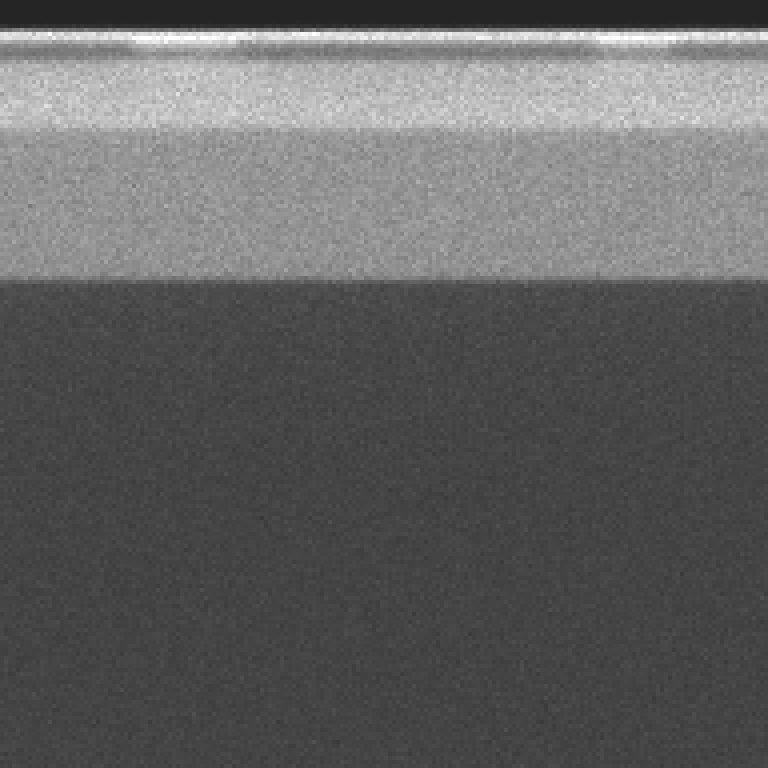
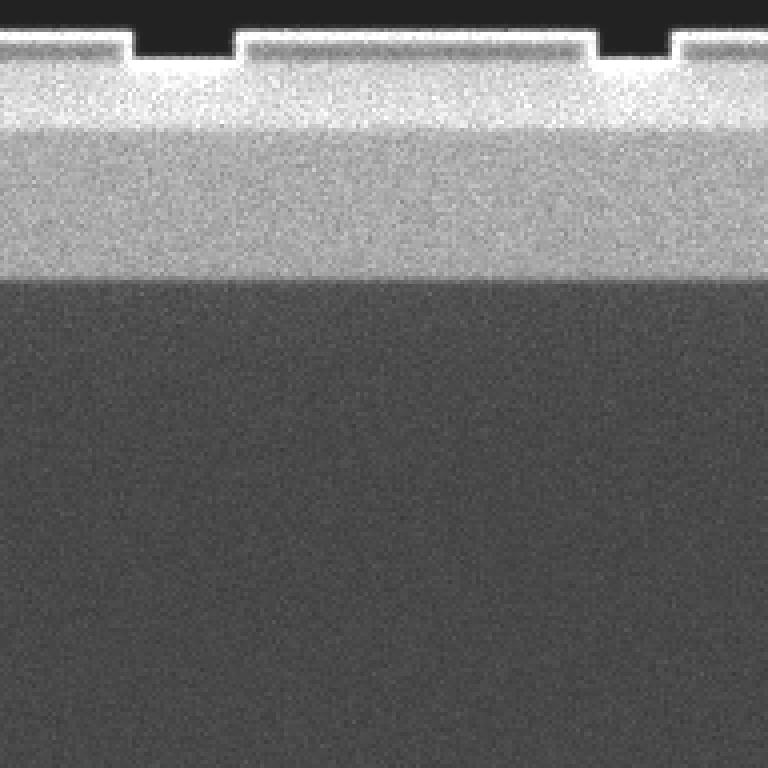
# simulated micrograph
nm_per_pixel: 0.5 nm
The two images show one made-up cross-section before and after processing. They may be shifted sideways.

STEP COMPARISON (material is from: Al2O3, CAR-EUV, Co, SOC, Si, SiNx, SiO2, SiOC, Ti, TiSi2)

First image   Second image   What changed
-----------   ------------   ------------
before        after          SOC, removed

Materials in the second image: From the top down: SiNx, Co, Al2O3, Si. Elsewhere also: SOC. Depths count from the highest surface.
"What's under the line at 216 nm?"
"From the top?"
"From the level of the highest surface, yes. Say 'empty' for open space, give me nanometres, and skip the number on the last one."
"SiNx 14, Co 34, Al2O3 76, Si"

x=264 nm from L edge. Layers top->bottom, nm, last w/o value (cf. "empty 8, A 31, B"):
SiNx 14, Co 34, Al2O3 76, Si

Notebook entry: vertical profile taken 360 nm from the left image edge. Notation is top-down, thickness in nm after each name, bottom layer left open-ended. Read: SiNx 14, Co 34, Al2O3 76, Si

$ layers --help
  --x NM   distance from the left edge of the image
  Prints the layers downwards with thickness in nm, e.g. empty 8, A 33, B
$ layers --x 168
SiNx 14, Co 34, Al2O3 76, Si